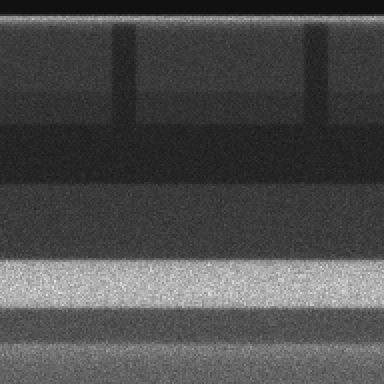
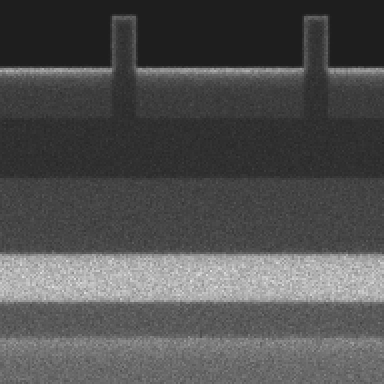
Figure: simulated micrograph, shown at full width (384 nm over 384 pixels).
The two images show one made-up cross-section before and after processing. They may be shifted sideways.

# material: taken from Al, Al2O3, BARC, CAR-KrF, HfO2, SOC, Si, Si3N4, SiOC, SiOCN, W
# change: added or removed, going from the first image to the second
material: SOC
change: removed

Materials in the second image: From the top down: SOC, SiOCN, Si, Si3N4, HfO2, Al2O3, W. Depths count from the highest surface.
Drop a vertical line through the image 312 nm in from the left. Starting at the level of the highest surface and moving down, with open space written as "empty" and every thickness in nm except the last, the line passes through Si 162, Si3N4 76, HfO2 48, Al2O3 36, W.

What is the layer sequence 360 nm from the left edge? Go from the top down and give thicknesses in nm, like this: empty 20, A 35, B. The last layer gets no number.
empty 52, SOC 18, SiOCN 32, Si 60, Si3N4 76, HfO2 48, Al2O3 36, W